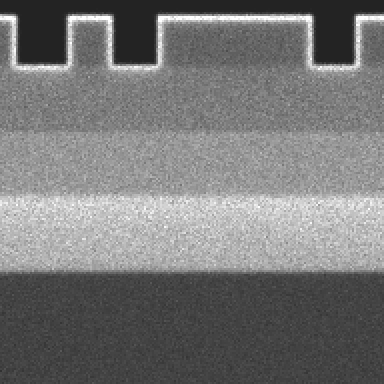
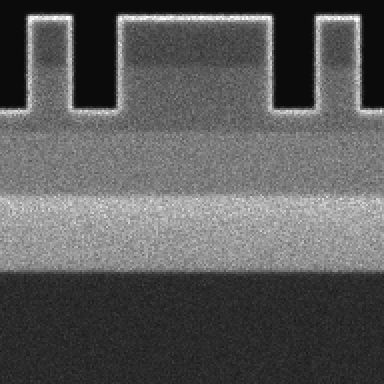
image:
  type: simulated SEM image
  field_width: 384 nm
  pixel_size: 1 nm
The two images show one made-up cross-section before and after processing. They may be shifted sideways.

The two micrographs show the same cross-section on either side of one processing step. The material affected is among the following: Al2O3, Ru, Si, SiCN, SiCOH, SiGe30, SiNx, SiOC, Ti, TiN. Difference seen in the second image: TiN removed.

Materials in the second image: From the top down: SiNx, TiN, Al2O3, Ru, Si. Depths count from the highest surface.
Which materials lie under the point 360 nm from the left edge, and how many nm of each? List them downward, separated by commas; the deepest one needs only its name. empty 94, TiN 22, Al2O3 64, Ru 76, Si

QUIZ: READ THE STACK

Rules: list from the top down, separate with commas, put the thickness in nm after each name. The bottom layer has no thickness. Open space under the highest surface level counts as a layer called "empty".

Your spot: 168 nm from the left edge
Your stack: SiNx 50, TiN 66, Al2O3 64, Ru 76, Si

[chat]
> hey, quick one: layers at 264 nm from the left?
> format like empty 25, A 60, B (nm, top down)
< SiNx 50, TiN 66, Al2O3 64, Ru 76, Si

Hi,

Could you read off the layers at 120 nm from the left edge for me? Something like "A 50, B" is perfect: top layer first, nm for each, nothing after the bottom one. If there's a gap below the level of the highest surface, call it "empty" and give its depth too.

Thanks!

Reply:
SiNx 50, TiN 66, Al2O3 64, Ru 76, Si